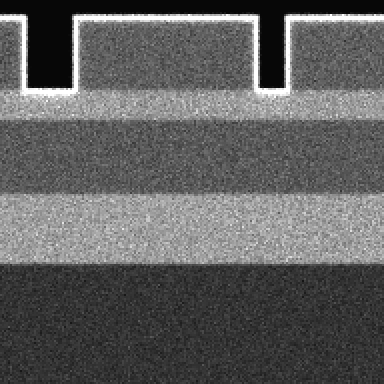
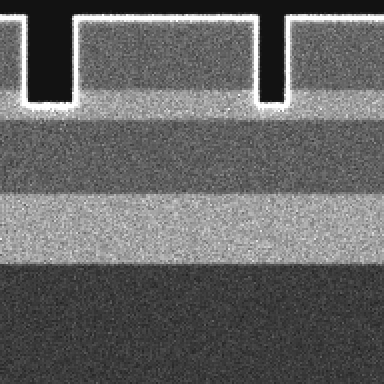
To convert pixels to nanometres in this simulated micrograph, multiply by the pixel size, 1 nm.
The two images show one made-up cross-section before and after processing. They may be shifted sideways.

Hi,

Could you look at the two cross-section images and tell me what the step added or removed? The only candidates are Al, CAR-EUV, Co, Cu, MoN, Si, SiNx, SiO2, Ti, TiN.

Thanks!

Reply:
removed Co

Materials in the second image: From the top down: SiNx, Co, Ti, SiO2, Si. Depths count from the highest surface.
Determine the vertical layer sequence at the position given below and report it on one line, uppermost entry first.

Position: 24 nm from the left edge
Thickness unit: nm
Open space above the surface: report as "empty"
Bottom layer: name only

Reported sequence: SiNx 74, Co 30, Ti 74, SiO2 70, Si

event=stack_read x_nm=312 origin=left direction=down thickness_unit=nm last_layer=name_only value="SiNx 74, Co 30, Ti 74, SiO2 70, Si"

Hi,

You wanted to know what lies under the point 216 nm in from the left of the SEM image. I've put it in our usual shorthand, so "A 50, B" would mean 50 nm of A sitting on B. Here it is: SiNx 74, Co 30, Ti 74, SiO2 70, Si